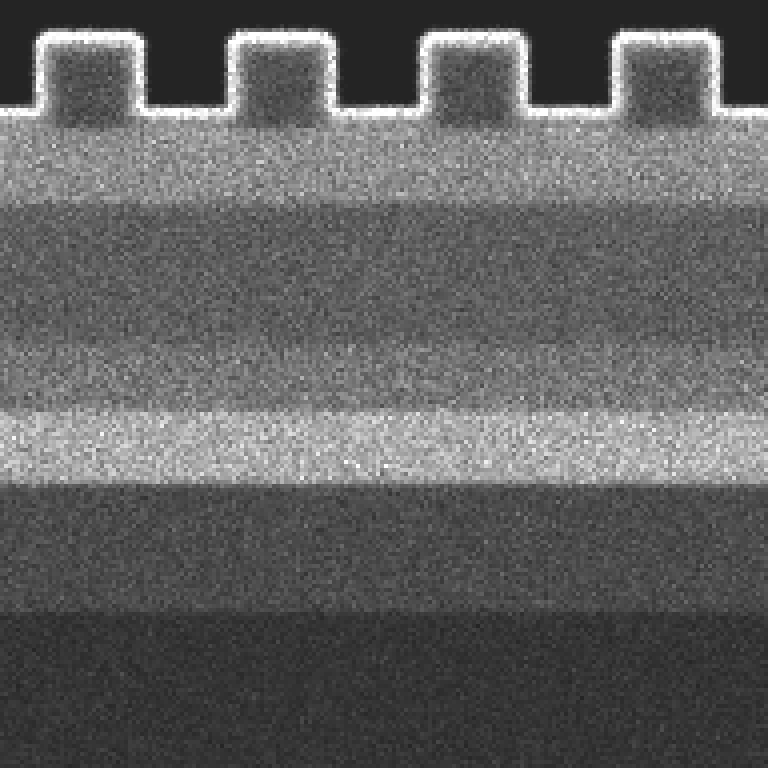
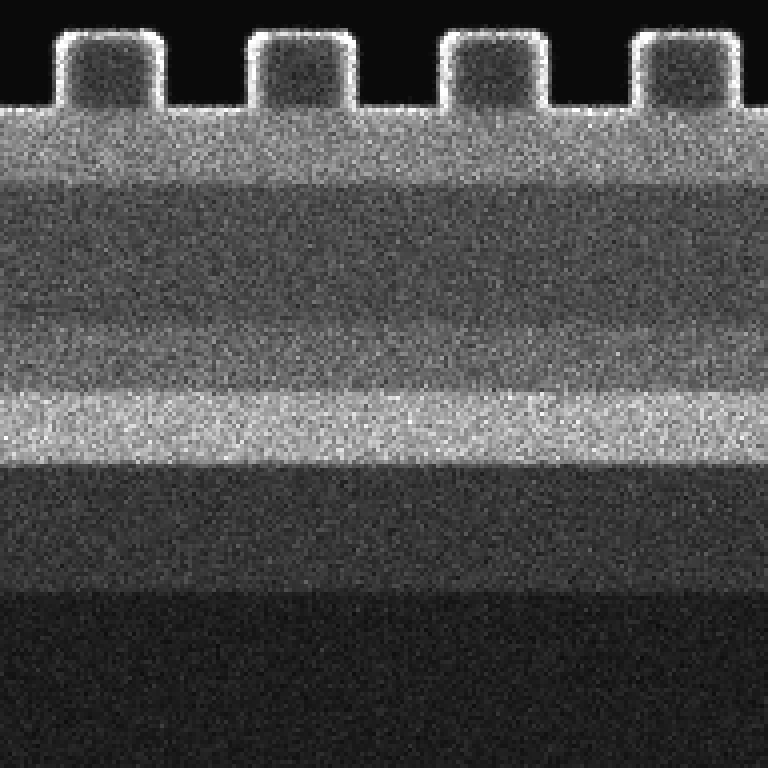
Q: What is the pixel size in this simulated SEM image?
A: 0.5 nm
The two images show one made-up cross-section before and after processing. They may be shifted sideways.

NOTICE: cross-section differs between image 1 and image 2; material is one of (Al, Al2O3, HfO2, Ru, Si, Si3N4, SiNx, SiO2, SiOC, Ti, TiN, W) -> removed: Al2O3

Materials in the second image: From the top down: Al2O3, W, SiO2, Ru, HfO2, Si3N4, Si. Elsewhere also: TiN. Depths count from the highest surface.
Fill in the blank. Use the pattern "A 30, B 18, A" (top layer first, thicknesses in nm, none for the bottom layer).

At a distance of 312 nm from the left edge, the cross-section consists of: empty 38, W 38, SiO2 70, Ru 34, HfO2 36, Si3N4 64, Si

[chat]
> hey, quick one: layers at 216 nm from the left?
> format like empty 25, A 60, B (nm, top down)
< empty 38, W 38, SiO2 70, Ru 34, HfO2 36, Si3N4 64, Si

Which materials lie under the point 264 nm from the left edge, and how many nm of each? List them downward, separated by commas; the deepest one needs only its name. Al2O3 38, W 38, SiO2 70, Ru 34, HfO2 36, Si3N4 64, Si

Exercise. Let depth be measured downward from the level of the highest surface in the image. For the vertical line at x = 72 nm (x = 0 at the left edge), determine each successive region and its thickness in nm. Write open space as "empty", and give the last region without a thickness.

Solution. Al2O3 38, W 38, SiO2 70, Ru 34, HfO2 36, Si3N4 64, Si